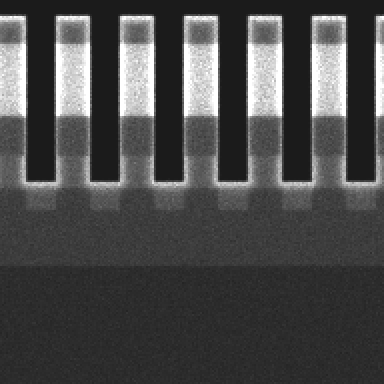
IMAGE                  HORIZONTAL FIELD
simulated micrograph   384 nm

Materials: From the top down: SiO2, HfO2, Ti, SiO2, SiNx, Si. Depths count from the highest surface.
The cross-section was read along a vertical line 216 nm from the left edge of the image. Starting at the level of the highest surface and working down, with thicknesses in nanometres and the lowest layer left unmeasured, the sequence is SiO2 28, HfO2 72, Ti 40, SiO2 32, SiNx 78, Si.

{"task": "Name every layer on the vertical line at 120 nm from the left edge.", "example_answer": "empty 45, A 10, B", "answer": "SiO2 28, HfO2 72, Ti 40, SiO2 32, SiNx 78, Si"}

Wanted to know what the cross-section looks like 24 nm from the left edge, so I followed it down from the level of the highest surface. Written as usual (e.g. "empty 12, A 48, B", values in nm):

SiO2 28, HfO2 72, Ti 40, SiO2 32, SiNx 78, Si